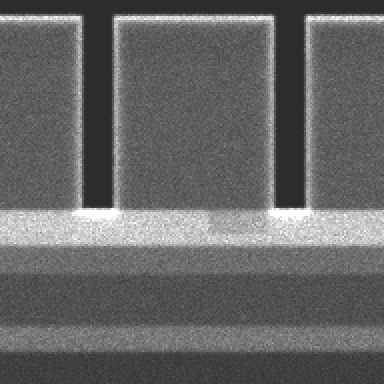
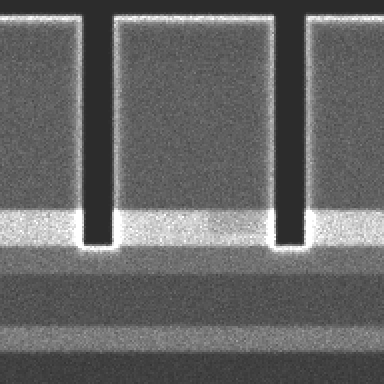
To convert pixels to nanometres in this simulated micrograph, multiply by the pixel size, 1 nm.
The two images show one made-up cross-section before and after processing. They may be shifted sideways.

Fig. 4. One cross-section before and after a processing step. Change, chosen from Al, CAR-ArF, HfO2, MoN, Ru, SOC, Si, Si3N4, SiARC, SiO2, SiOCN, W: HfO2 removed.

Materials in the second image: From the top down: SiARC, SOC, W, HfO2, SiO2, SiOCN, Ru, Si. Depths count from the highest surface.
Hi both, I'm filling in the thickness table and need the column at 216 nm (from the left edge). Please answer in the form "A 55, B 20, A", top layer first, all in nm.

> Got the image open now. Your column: SiARC 44, SOC 150, W 24, HfO2 12, SiO2 28, SiOCN 52, Ru 26, Si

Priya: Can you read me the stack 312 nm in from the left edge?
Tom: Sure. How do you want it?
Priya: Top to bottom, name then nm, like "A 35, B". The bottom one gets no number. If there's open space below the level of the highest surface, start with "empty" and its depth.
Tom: SiARC 44, SOC 150, HfO2 36, SiO2 28, SiOCN 52, Ru 26, Si